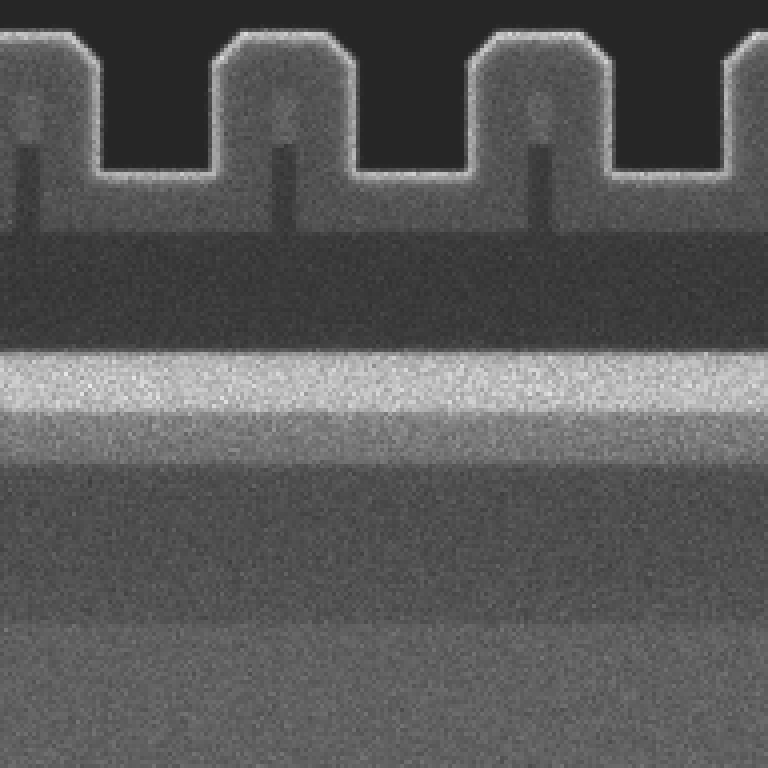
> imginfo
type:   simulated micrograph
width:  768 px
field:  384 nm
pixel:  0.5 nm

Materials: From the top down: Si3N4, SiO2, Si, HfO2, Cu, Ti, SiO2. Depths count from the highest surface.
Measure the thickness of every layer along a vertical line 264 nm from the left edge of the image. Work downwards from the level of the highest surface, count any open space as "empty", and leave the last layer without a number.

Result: Si3N4 30, SiO2 26, Si 104, HfO2 30, Cu 26, Ti 80, SiO2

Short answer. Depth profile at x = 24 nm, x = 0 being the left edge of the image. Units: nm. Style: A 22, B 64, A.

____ Si3N4 100, Si 60, HfO2 30, Cu 26, Ti 80, SiO2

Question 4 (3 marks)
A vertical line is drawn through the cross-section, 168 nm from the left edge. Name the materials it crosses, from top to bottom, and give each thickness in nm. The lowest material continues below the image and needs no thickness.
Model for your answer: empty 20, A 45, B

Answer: empty 6, Si3N4 94, Si 60, HfO2 30, Cu 26, Ti 80, SiO2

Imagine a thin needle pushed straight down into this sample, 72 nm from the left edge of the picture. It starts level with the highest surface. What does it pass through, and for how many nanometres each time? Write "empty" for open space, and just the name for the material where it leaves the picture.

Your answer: empty 70, Si3N4 30, Si 60, HfO2 30, Cu 26, Ti 80, SiO2